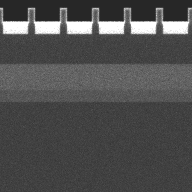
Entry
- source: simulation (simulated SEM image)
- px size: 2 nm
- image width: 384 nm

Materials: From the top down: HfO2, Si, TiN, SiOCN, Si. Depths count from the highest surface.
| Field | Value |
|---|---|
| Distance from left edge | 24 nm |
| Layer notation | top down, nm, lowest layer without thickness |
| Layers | empty 28, HfO2 24, Si 60, TiN 52, SiOCN 24, Si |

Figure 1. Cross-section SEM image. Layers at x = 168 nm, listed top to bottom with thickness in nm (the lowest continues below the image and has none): empty 28, HfO2 24, Si 60, TiN 52, SiOCN 24, Si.